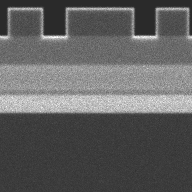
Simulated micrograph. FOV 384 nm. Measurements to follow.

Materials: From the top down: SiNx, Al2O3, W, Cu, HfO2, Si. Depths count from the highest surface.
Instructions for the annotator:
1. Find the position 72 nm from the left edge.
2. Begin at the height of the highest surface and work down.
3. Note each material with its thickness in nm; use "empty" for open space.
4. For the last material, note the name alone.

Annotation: SiNx 56, Al2O3 58, W 50, Cu 10, HfO2 36, Si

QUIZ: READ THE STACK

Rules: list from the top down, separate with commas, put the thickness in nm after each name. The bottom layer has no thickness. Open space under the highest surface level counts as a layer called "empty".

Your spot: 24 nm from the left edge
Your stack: SiNx 56, Al2O3 58, W 50, Cu 10, HfO2 36, Si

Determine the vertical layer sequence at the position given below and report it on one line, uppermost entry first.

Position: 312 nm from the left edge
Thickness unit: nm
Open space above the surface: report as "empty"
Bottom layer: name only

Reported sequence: SiNx 56, Al2O3 58, W 50, Cu 10, HfO2 36, Si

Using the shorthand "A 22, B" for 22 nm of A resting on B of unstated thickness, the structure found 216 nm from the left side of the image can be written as SiNx 56, Al2O3 58, W 50, Cu 10, HfO2 36, Si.